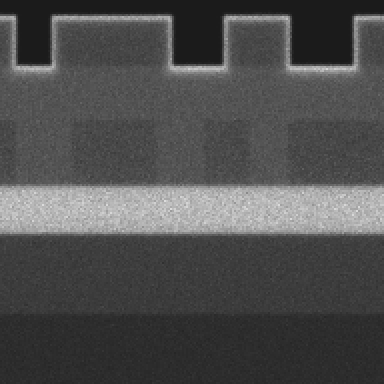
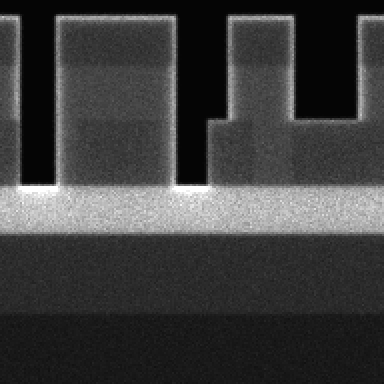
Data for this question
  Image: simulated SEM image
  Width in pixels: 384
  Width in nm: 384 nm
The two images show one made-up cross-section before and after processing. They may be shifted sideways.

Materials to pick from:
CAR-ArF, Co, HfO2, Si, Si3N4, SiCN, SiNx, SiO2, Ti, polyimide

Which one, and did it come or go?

SiO2 - removed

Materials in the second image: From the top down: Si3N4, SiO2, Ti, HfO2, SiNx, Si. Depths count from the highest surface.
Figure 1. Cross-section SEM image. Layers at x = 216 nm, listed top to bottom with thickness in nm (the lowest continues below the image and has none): empty 104, Ti 66, HfO2 48, SiNx 80, Si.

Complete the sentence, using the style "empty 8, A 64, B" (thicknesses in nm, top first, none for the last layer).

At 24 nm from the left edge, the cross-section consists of empty 170, HfO2 48, SiNx 80, Si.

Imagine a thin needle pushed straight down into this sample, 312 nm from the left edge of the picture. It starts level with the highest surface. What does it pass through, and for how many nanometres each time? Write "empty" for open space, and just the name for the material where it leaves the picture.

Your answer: empty 104, Ti 66, HfO2 48, SiNx 80, Si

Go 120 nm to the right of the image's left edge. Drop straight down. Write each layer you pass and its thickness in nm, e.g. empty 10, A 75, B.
Si3N4 50, SiO2 54, Ti 66, HfO2 48, SiNx 80, Si